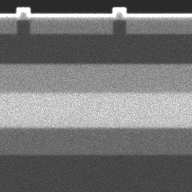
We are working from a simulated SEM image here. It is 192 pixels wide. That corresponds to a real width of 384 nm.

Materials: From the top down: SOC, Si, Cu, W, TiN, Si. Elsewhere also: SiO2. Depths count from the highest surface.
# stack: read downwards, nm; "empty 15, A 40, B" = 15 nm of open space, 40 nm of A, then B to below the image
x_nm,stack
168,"empty 12, SOC 40, Si 60, Cu 58, W 70, TiN 54, Si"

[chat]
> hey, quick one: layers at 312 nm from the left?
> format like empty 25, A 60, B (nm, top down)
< empty 12, SOC 40, Si 60, Cu 58, W 70, TiN 54, Si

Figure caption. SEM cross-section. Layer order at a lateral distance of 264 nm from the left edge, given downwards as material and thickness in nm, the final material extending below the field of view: empty 12, SOC 40, Si 60, Cu 58, W 70, TiN 54, Si